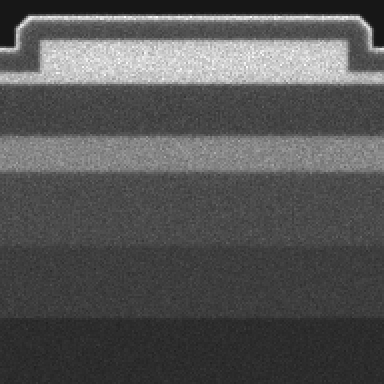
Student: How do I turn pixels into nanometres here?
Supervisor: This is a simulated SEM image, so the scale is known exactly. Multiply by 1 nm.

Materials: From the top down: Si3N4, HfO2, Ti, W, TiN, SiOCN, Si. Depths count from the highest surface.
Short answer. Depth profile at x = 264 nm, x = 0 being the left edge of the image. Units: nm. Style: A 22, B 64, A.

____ Si3N4 24, HfO2 44, Ti 52, W 36, TiN 74, SiOCN 72, Si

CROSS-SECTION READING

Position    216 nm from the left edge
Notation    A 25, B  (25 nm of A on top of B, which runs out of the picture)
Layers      Si3N4 24, HfO2 44, Ti 52, W 36, TiN 74, SiOCN 72, Si